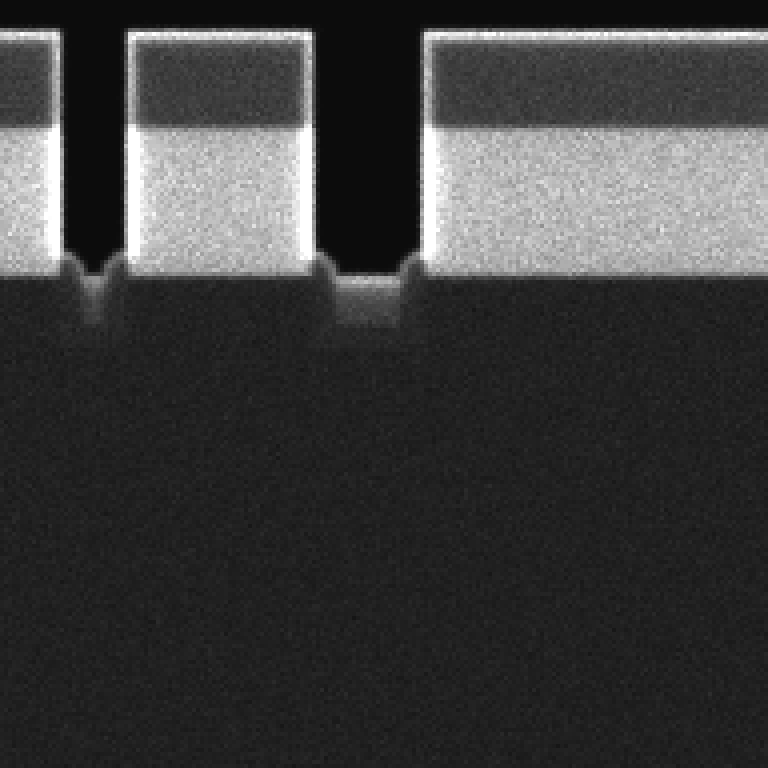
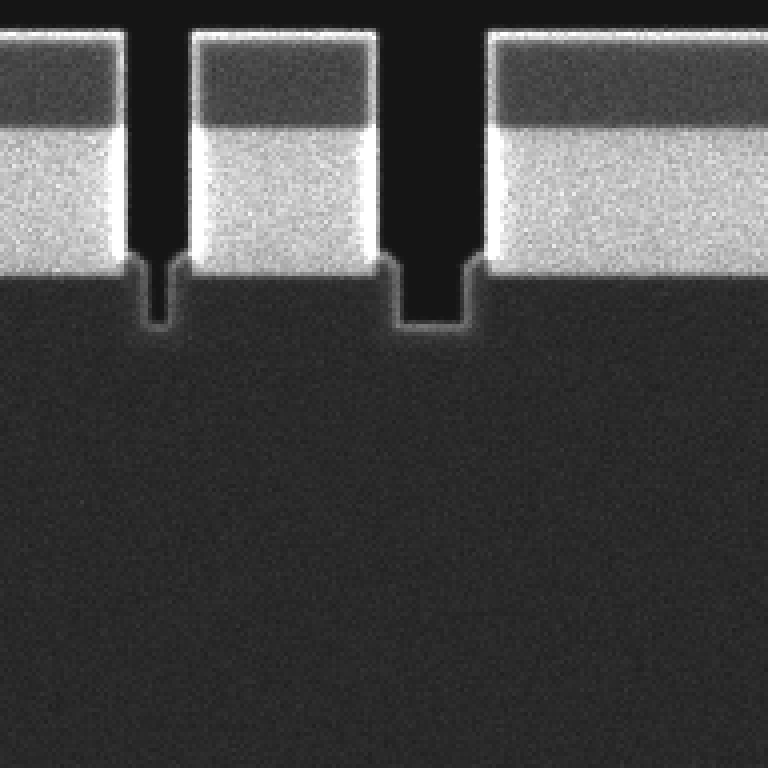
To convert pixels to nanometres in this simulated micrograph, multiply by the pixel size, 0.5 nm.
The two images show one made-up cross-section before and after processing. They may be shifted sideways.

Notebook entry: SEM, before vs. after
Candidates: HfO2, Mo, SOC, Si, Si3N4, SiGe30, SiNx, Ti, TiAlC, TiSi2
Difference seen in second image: SOC removed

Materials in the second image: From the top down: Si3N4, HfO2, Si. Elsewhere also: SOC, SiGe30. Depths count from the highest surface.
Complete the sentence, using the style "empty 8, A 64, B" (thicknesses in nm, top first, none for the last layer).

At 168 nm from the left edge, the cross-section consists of Si3N4 48, HfO2 74, Si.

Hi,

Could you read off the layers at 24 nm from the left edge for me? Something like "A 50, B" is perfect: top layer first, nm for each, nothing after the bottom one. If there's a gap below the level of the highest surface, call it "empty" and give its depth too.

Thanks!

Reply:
Si3N4 48, HfO2 74, Si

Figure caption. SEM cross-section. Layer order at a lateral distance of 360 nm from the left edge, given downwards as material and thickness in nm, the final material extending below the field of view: Si3N4 48, HfO2 74, Si